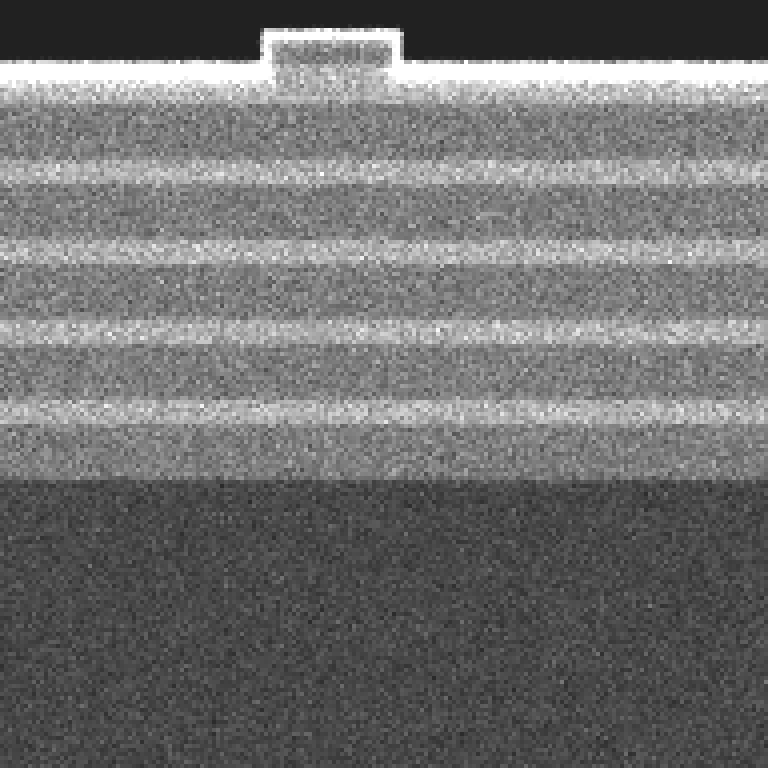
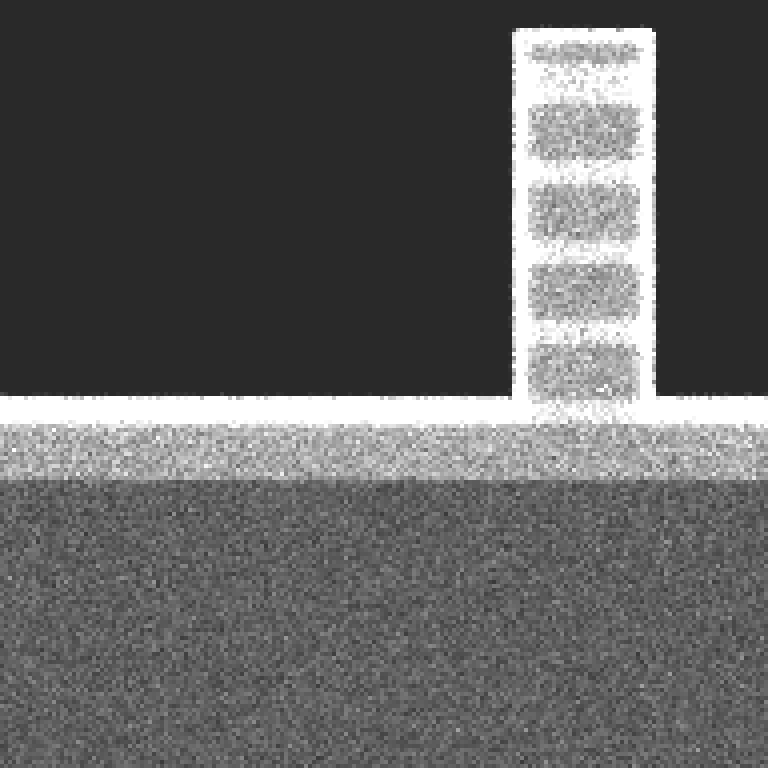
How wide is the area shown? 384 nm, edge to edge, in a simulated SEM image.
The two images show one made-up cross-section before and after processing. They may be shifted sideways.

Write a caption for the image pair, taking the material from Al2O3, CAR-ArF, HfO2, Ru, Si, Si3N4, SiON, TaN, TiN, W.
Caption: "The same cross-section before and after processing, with Al2O3 and Si3N4 removed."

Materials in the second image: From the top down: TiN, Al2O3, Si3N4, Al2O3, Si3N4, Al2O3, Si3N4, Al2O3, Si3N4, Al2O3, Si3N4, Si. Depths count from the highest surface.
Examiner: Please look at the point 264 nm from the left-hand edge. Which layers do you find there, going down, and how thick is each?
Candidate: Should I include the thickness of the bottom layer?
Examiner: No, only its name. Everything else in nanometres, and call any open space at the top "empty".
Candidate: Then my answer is TiN 16, Al2O3 20, Si3N4 28, Al2O3 12, Si3N4 28, Al2O3 12, Si3N4 28, Al2O3 12, Si3N4 28, Al2O3 12, Si3N4 28, Si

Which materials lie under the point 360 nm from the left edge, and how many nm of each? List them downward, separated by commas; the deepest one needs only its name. empty 184, Al2O3 12, Si3N4 28, Si